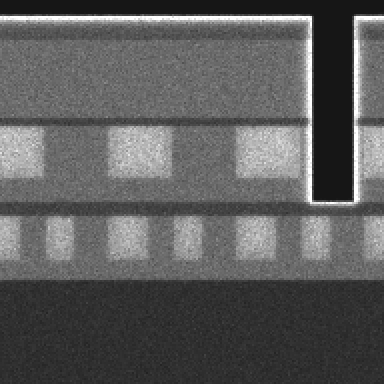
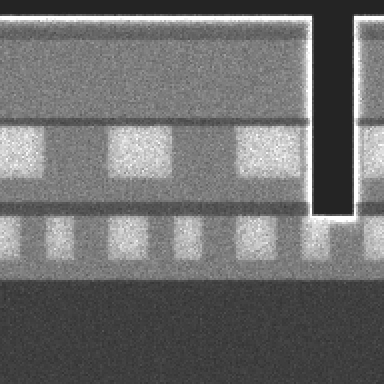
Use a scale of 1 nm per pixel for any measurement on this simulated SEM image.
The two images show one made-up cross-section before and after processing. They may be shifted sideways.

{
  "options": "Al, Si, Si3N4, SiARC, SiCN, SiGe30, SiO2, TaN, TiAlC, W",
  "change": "removed",
  "material": "SiCN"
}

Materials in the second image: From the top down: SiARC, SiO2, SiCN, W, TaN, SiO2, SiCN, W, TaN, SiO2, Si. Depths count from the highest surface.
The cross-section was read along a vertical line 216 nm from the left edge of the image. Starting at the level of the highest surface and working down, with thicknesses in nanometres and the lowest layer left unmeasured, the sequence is SiARC 24, SiO2 78, SiCN 8, SiO2 76, SiCN 14, SiO2 64, Si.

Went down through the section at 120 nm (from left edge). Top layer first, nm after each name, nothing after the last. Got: SiARC 24, SiO2 78, SiCN 8, W 42, TaN 10, SiO2 24, SiCN 14, W 34, TaN 10, SiO2 20, Si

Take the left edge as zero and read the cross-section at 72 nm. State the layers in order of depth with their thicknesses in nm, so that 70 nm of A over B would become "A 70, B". SiARC 24, SiO2 78, SiCN 8, SiO2 76, SiCN 14, TaN 44, SiO2 20, Si